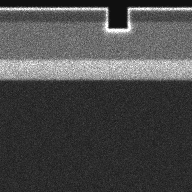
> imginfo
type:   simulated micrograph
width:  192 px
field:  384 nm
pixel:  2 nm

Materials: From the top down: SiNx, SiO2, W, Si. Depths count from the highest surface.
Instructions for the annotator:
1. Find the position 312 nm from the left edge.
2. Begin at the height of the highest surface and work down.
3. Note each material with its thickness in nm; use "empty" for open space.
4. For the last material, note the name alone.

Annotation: SiNx 28, SiO2 76, W 40, Si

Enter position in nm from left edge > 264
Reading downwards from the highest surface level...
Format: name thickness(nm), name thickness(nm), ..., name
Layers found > SiNx 28, SiO2 76, W 40, Si